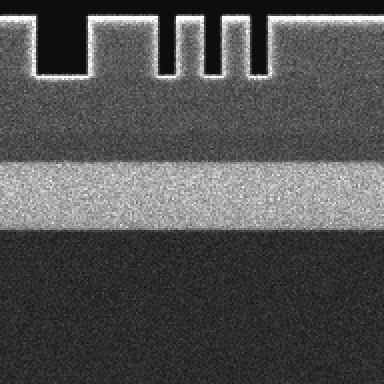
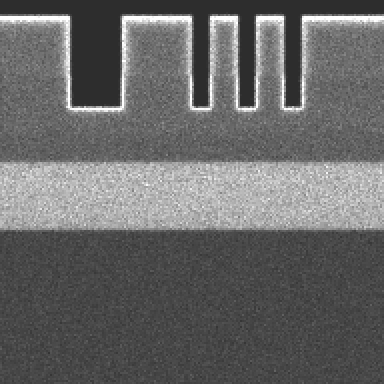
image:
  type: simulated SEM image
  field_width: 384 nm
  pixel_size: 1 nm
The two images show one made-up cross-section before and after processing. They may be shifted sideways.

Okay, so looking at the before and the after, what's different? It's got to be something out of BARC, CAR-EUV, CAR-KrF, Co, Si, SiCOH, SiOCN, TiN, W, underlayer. TiN, removed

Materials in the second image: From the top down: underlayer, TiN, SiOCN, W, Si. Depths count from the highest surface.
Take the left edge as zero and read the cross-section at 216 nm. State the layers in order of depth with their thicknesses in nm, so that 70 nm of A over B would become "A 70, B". underlayer 60, TiN 58, SiOCN 28, W 68, Si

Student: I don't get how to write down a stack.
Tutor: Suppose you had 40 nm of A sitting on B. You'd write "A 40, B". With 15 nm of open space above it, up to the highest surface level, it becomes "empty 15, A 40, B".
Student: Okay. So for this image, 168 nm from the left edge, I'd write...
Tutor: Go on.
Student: underlayer 60, TiN 58, SiOCN 28, W 68, Si